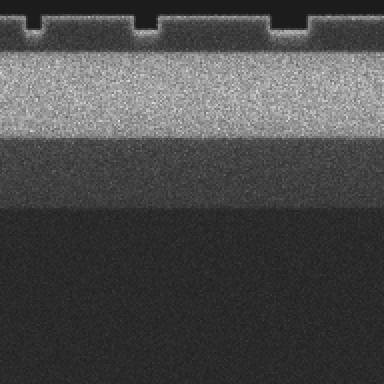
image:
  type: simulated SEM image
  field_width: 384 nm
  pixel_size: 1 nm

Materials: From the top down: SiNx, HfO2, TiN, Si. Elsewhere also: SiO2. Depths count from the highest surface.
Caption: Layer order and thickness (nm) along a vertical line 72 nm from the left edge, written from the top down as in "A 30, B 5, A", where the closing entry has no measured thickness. SiNx 36, HfO2 86, TiN 70, Si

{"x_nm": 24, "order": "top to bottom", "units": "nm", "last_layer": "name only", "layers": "SiNx 36, HfO2 86, TiN 70, Si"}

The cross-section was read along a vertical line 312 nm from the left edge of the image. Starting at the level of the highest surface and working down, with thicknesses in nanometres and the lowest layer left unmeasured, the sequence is SiNx 36, HfO2 86, TiN 70, Si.